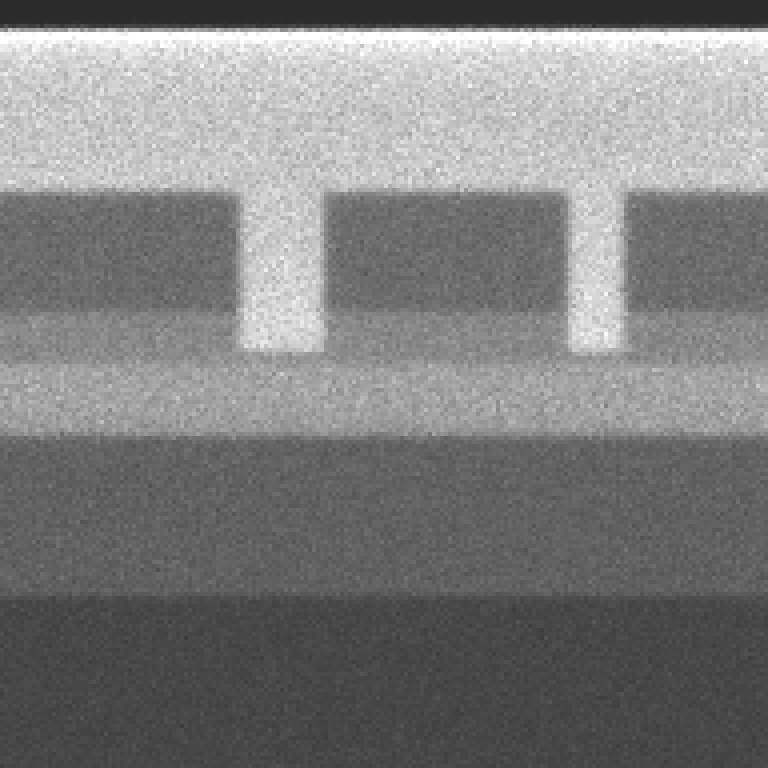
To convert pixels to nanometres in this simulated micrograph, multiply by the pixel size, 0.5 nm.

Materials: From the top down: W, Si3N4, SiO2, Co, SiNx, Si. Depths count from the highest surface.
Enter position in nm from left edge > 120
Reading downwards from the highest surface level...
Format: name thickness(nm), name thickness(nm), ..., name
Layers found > W 160, SiO2 6, Co 36, SiNx 80, Si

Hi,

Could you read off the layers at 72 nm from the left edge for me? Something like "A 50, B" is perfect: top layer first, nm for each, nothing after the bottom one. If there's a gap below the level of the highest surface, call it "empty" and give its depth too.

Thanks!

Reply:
W 80, Si3N4 60, SiO2 26, Co 36, SiNx 80, Si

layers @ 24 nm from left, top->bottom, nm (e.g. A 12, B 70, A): W 80, Si3N4 60, SiO2 26, Co 36, SiNx 80, Si